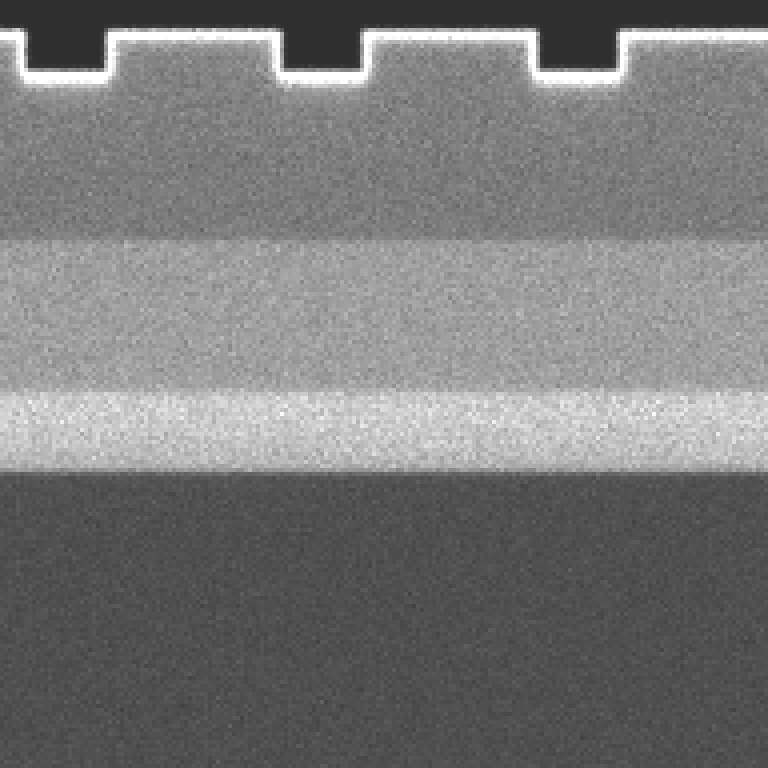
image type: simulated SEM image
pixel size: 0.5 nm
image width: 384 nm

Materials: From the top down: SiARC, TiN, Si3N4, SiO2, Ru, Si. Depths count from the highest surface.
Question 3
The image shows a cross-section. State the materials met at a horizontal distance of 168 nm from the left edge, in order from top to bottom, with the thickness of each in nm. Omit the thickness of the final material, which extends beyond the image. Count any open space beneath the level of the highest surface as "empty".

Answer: empty 20, SiARC 12, TiN 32, Si3N4 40, SiO2 76, Ru 40, Si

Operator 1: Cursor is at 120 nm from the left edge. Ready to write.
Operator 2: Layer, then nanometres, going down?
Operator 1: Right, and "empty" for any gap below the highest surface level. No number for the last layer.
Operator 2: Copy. TiN 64, Si3N4 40, SiO2 76, Ru 40, Si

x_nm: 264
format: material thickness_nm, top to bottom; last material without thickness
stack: TiN 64, Si3N4 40, SiO2 76, Ru 40, Si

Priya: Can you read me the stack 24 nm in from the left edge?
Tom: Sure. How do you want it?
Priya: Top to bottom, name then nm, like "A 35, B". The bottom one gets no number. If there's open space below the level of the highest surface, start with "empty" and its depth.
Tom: empty 20, SiARC 12, TiN 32, Si3N4 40, SiO2 76, Ru 40, Si